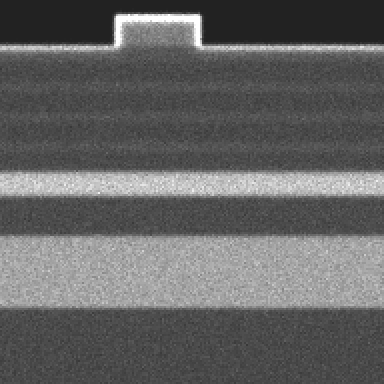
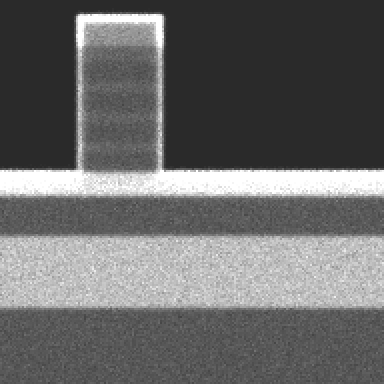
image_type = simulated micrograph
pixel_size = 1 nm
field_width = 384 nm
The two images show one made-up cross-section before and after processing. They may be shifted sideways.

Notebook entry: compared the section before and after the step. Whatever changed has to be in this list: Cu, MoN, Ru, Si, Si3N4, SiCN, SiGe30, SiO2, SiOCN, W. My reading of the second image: Si and SiGe30 removed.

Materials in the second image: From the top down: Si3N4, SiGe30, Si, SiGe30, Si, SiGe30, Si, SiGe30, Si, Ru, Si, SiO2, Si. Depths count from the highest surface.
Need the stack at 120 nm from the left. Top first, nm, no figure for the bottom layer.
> Si3N4 30, SiGe30 16, Si 20, SiGe30 10, Si 20, SiGe30 10, Si 20, SiGe30 10, Si 20, Ru 24, Si 40, SiO2 72, Si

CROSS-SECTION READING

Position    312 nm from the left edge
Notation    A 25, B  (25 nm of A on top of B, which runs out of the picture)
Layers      empty 156, Ru 24, Si 40, SiO2 72, Si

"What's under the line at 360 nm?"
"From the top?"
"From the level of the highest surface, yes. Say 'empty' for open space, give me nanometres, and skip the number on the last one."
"empty 156, Ru 24, Si 40, SiO2 72, Si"